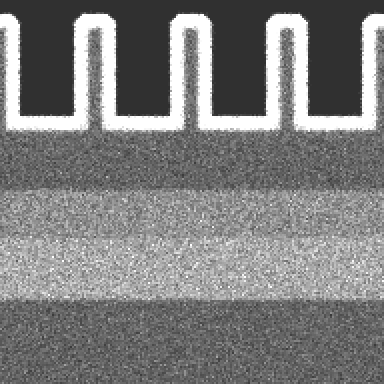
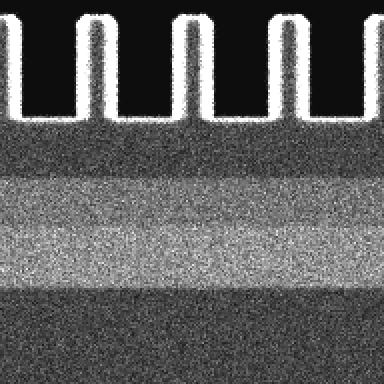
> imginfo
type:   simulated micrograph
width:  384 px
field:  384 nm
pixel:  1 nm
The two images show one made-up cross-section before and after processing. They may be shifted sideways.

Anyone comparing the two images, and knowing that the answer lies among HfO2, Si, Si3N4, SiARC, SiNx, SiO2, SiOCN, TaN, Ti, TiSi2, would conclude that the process removed SiO2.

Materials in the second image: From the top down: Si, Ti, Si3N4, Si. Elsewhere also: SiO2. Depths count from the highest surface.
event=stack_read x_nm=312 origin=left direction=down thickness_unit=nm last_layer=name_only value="empty 102, Si 60, Ti 48, Si3N4 62, Si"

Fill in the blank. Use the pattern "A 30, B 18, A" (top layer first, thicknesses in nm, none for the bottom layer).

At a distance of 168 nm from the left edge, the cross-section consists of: empty 102, Si 60, Ti 48, Si3N4 62, Si